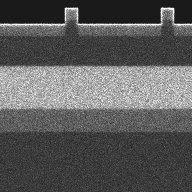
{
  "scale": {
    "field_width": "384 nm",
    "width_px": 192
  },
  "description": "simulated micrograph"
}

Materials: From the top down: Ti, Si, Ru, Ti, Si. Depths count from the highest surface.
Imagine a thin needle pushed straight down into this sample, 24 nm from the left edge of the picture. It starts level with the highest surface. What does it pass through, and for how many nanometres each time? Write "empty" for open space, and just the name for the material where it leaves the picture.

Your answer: empty 32, Ti 24, Si 60, Ru 86, Ti 46, Si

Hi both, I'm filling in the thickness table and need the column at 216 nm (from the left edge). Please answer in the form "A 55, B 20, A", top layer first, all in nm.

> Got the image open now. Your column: empty 32, Ti 24, Si 60, Ru 86, Ti 46, Si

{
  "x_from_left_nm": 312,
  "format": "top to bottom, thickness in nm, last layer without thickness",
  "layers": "empty 32, Ti 24, Si 60, Ru 86, Ti 46, Si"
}